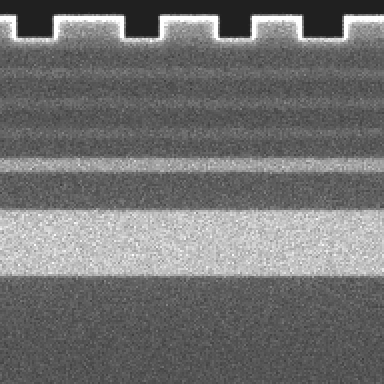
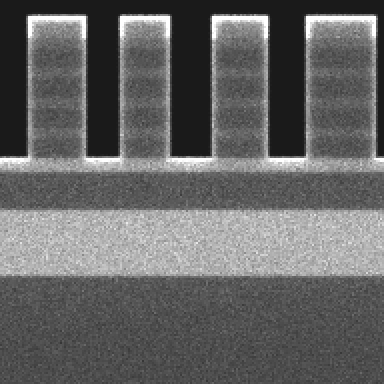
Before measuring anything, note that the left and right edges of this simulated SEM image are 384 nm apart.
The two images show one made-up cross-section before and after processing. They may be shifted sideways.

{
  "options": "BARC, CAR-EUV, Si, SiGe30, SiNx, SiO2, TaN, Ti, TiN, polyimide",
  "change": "removed",
  "material": "Si and SiGe30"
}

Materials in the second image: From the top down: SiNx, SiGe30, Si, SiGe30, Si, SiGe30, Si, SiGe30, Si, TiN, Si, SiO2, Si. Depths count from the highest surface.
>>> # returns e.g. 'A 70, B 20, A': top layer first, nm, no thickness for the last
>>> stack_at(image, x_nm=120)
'SiNx 22, SiGe30 10, Si 20, SiGe30 10, Si 20, SiGe30 10, Si 20, SiGe30 10, Si 20, TiN 14, Si 38, SiO2 66, Si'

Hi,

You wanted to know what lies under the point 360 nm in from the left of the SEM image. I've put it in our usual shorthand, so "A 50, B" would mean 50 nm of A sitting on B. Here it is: SiNx 22, SiGe30 10, Si 20, SiGe30 10, Si 20, SiGe30 10, Si 20, SiGe30 10, Si 20, TiN 14, Si 38, SiO2 66, Si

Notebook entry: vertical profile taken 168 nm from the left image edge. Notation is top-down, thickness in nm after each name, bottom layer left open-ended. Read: SiNx 22, SiGe30 10, Si 20, SiGe30 10, Si 20, SiGe30 10, Si 20, SiGe30 10, Si 20, TiN 14, Si 38, SiO2 66, Si